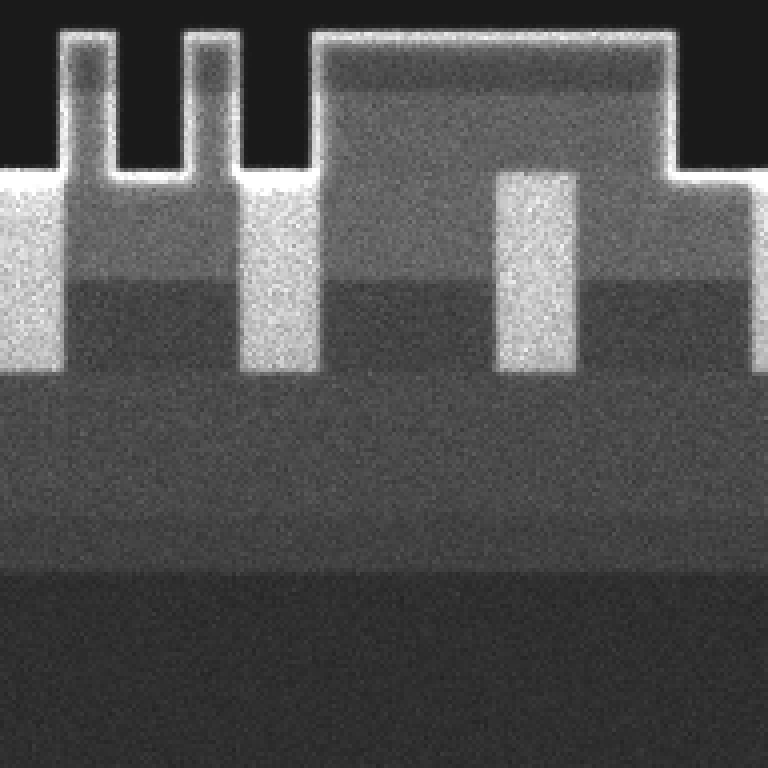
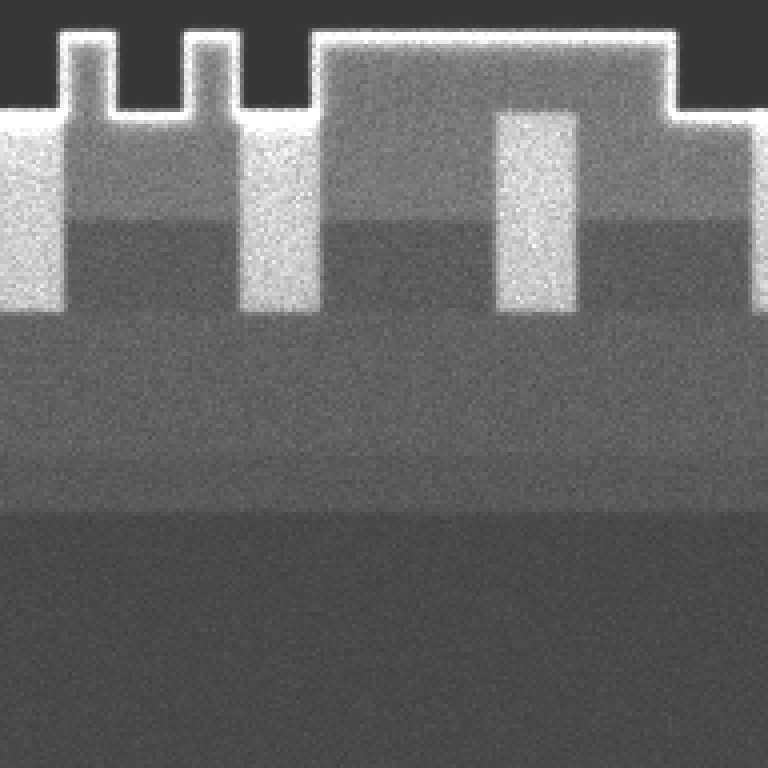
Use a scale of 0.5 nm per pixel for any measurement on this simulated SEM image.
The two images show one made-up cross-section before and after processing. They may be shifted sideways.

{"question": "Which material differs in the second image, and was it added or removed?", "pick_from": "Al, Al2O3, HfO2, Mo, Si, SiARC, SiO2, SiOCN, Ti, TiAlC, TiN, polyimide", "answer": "SiARC, removed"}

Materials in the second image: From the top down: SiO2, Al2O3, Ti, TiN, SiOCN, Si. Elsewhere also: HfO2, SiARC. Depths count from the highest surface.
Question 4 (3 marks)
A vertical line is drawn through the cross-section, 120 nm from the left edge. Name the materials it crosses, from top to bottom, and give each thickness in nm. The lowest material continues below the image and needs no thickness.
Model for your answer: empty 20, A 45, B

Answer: empty 40, HfO2 100, TiN 72, SiOCN 28, Si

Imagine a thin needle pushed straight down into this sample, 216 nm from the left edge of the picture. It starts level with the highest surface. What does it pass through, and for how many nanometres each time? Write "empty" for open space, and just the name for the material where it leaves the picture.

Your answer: SiO2 40, Al2O3 54, Ti 46, TiN 72, SiOCN 28, Si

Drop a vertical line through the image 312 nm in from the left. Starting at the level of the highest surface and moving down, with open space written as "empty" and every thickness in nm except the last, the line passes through SiO2 40, Al2O3 54, Ti 46, TiN 72, SiOCN 28, Si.